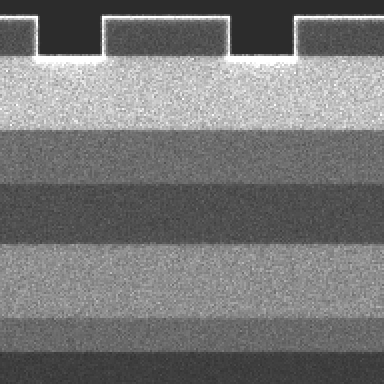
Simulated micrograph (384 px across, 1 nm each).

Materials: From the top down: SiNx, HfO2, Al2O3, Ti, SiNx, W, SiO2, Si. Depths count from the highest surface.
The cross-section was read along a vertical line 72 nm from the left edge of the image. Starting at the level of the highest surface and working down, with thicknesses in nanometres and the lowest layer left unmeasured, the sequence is empty 40, HfO2 74, Al2O3 54, Ti 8, SiNx 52, W 74, SiO2 34, Si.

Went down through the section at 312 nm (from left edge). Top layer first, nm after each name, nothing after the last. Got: SiNx 40, HfO2 74, Al2O3 54, Ti 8, SiNx 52, W 74, SiO2 34, Si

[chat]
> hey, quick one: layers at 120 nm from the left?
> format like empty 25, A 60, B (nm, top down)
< SiNx 40, HfO2 74, Al2O3 54, Ti 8, SiNx 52, W 74, SiO2 34, Si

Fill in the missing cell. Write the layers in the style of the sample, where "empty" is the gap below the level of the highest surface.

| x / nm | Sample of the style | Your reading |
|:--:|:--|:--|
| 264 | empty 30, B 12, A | empty 40, HfO2 74, Al2O3 54, Ti 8, SiNx 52, W 74, SiO2 34, Si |